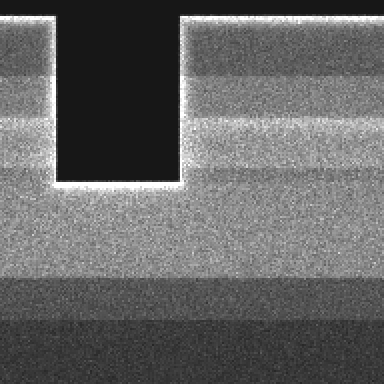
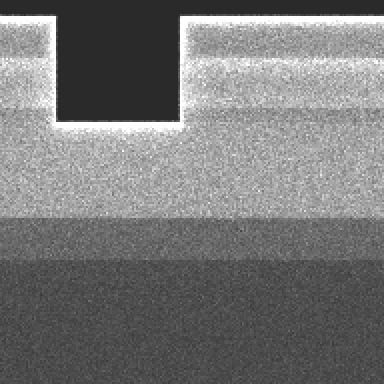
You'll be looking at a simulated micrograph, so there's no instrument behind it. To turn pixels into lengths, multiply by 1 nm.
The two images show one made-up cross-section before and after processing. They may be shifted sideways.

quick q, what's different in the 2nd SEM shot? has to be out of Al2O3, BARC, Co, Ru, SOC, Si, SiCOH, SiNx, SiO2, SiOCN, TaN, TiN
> SOC removed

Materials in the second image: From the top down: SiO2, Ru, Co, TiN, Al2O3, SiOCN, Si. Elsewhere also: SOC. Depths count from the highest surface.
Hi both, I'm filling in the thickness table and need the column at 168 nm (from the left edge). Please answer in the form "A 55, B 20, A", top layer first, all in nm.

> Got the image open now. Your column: empty 106, Al2O3 96, SiOCN 42, Si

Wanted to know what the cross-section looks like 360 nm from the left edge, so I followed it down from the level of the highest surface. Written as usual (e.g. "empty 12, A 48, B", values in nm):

SiO2 42, Ru 40, Co 10, TiN 14, Al2O3 96, SiOCN 42, Si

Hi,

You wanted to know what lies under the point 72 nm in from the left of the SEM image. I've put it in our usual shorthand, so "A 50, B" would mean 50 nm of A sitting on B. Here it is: empty 106, Al2O3 96, SiOCN 42, Si